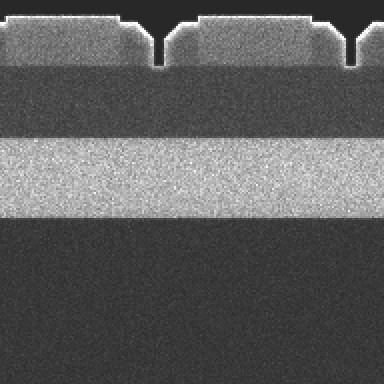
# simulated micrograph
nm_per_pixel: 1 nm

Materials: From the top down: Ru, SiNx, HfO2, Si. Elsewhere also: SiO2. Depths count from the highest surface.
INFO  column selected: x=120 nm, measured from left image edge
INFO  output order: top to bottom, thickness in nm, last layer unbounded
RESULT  empty 6, SiO2 44, SiNx 72, HfO2 80, Si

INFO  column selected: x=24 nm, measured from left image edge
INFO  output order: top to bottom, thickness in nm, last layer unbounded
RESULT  Ru 50, SiNx 72, HfO2 80, Si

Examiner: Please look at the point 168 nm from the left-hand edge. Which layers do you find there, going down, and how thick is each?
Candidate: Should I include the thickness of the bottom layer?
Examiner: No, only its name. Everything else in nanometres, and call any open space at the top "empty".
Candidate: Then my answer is empty 18, SiO2 32, SiNx 72, HfO2 80, Si